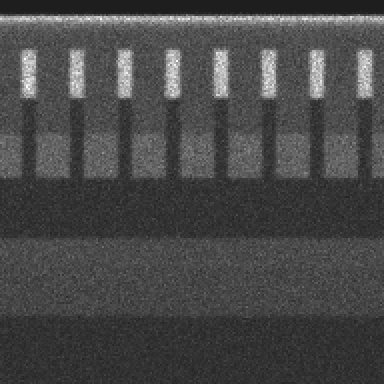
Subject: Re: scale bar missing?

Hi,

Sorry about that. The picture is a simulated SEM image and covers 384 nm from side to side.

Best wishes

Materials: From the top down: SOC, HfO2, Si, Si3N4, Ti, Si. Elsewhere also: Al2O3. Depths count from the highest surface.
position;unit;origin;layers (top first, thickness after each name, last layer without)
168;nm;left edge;SOC 34, HfO2 48, Si 140, Si3N4 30, Ti 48, Si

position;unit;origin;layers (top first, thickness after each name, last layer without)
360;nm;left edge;SOC 34, HfO2 48, Si 140, Si3N4 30, Ti 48, Si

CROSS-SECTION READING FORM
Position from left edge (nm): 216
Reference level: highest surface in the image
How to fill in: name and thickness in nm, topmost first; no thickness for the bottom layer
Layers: SOC 34, HfO2 48, Si 140, Si3N4 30, Ti 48, Si